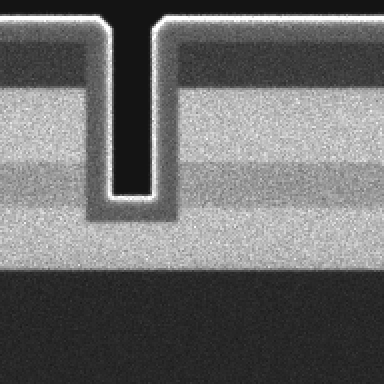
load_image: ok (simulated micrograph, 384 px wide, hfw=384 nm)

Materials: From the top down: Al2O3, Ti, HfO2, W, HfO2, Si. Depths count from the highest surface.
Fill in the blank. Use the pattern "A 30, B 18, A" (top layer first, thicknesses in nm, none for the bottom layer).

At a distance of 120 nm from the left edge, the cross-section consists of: empty 180, Al2O3 26, HfO2 48, Si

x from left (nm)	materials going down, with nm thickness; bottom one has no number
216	Al2O3 26, Ti 46, HfO2 74, W 46, HfO2 62, Si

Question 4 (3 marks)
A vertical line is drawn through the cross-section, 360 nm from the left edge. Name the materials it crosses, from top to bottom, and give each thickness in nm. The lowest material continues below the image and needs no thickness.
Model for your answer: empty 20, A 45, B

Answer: Al2O3 26, Ti 46, HfO2 74, W 46, HfO2 62, Si